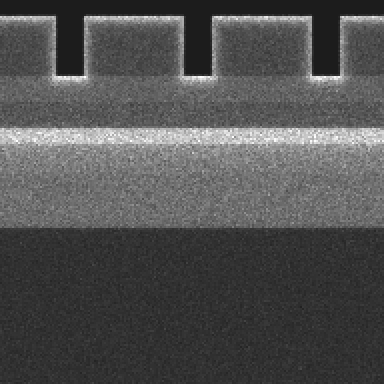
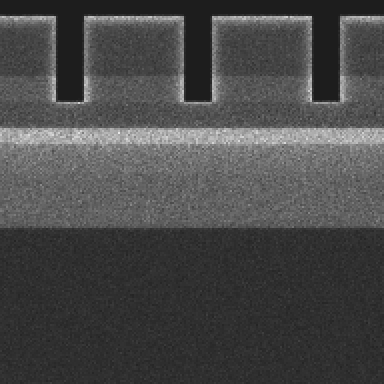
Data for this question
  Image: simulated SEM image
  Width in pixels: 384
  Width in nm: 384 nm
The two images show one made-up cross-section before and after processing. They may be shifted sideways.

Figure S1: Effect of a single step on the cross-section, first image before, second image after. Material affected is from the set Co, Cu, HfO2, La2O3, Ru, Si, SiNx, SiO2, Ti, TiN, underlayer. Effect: removed SiO2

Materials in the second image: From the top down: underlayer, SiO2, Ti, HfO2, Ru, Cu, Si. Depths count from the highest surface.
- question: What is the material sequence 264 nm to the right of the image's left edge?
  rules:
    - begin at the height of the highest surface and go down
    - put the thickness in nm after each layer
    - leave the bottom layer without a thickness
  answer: underlayer 60, SiO2 26, Ti 26, HfO2 16, Ru 30, Cu 54, Si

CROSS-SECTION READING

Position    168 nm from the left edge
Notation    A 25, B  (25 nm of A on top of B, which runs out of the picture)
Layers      underlayer 60, SiO2 26, Ti 26, HfO2 16, Ru 30, Cu 54, Si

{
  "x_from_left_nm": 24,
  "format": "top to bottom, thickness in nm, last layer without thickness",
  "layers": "underlayer 60, SiO2 26, Ti 26, HfO2 16, Ru 30, Cu 54, Si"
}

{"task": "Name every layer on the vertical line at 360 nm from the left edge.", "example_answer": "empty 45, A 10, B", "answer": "underlayer 60, SiO2 26, Ti 26, HfO2 16, Ru 30, Cu 54, Si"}